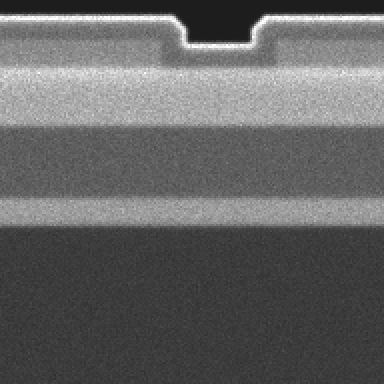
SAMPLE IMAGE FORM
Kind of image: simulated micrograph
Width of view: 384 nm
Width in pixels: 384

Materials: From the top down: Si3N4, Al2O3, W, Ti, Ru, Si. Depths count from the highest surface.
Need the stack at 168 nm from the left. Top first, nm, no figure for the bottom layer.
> Si3N4 52, W 58, Ti 72, Ru 28, Si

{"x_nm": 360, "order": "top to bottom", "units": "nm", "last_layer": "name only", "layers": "Si3N4 24, Al2O3 28, W 58, Ti 72, Ru 28, Si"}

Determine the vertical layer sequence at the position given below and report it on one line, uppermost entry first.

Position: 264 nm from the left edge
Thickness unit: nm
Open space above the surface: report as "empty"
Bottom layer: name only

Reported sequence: Si3N4 52, W 58, Ti 72, Ru 28, Si